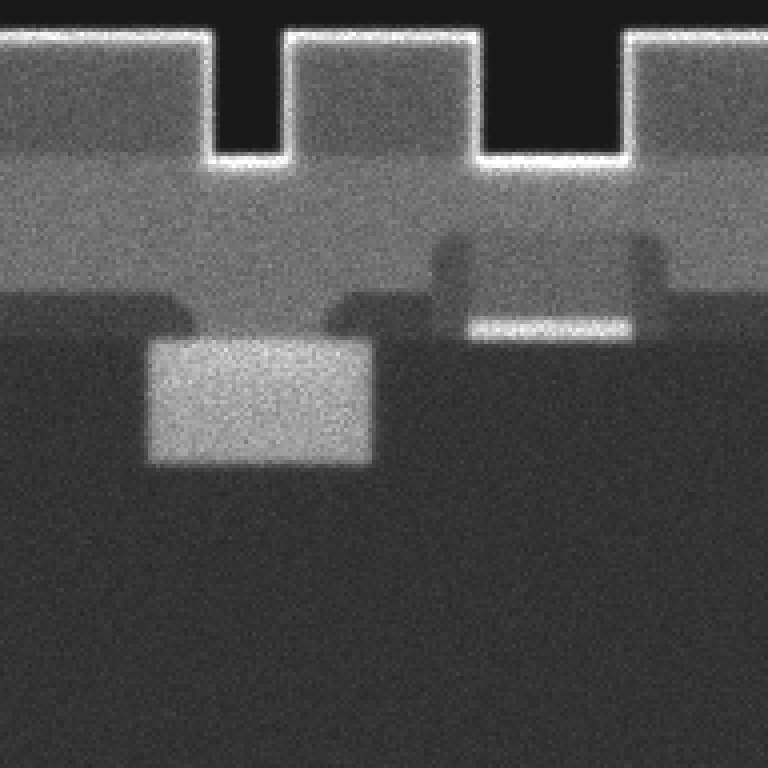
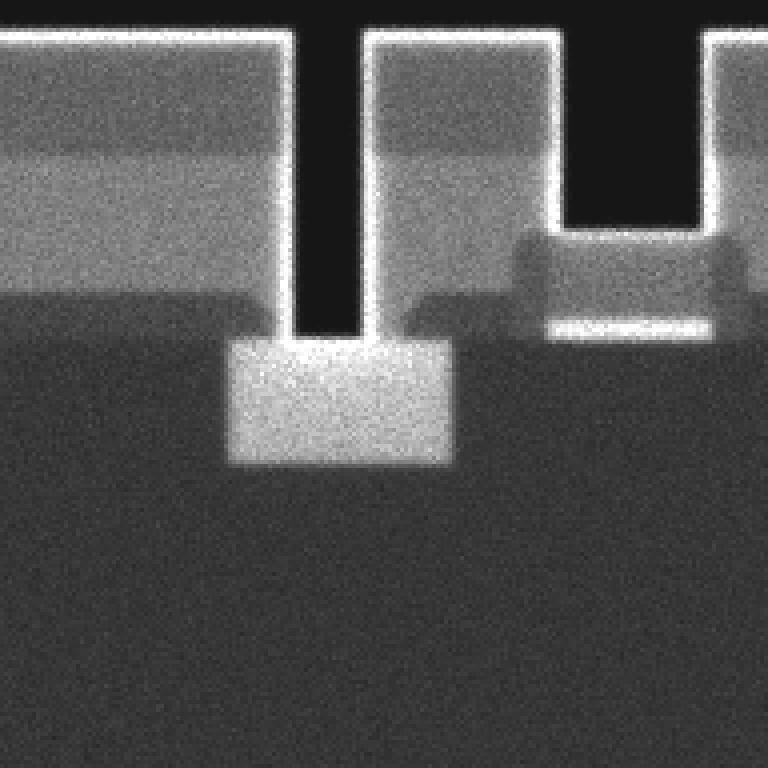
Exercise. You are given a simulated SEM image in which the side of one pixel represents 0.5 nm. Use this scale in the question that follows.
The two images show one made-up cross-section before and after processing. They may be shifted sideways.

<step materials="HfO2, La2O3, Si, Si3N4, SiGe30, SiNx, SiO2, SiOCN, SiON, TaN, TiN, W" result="removed SiO2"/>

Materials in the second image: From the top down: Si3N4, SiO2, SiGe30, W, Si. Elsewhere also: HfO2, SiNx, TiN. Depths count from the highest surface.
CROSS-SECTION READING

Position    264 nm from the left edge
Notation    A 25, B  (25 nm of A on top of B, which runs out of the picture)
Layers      Si3N4 62, SiO2 38, SiNx 54, Si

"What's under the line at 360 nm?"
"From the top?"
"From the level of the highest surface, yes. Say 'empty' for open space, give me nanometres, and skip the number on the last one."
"Si3N4 62, SiO2 38, SiNx 54, Si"